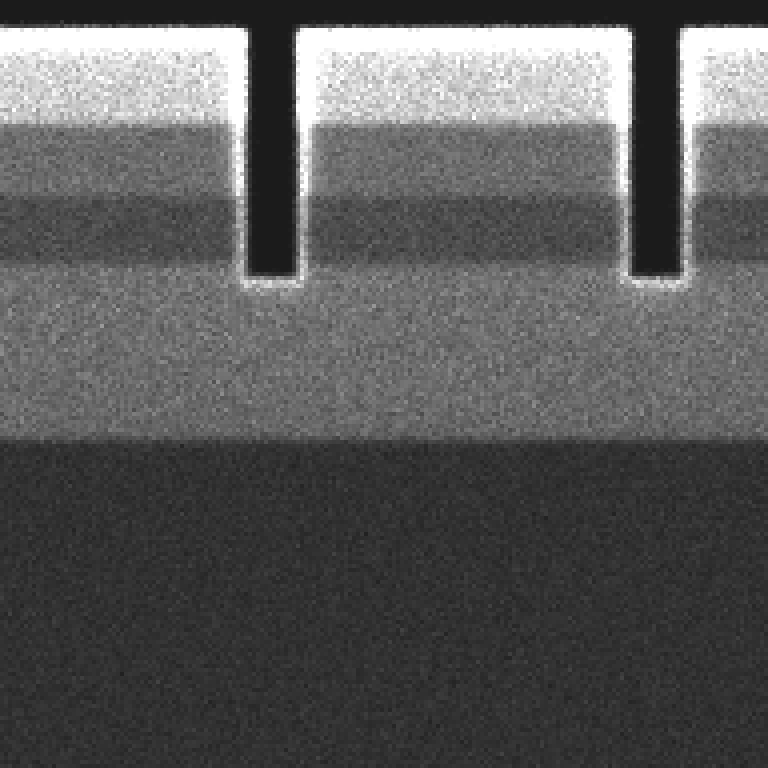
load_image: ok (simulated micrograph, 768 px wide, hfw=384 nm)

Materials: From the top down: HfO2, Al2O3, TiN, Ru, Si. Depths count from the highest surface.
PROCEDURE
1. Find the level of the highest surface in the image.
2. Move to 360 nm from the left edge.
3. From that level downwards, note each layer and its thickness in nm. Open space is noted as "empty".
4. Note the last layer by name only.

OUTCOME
HfO2 46, Al2O3 36, TiN 34, Ru 88, Si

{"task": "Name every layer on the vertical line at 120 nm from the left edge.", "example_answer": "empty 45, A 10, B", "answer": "HfO2 46, Al2O3 36, TiN 34, Ru 88, Si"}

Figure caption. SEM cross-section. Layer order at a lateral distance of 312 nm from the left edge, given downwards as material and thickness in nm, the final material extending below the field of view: HfO2 46, Al2O3 36, TiN 34, Ru 88, Si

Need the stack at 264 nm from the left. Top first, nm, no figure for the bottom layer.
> HfO2 46, Al2O3 36, TiN 34, Ru 88, Si